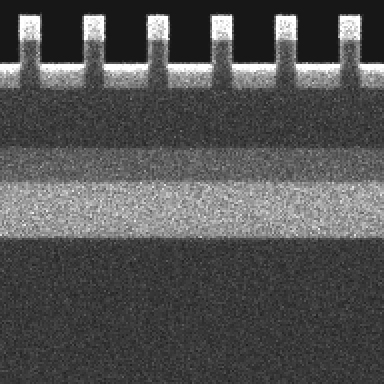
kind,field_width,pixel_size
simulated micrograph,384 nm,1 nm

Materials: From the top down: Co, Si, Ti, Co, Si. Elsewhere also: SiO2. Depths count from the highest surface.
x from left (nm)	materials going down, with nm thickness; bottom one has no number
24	Co 24, Si 108, Ti 34, Co 56, Si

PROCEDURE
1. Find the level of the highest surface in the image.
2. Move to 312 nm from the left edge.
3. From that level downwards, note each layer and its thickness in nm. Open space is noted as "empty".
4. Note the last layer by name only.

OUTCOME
empty 48, SiO2 24, Si 60, Ti 34, Co 56, Si